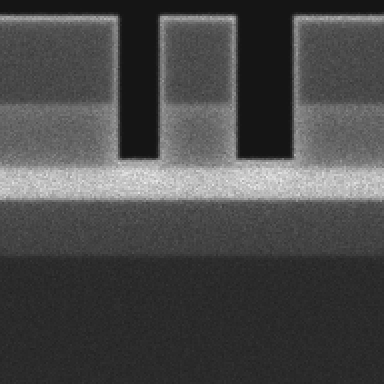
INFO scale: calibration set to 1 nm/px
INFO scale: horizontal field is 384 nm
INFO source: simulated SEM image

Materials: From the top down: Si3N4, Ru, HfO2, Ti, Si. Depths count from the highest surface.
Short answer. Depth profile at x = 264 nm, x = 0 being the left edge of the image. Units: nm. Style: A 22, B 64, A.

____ empty 144, Ru 8, HfO2 32, Ti 56, Si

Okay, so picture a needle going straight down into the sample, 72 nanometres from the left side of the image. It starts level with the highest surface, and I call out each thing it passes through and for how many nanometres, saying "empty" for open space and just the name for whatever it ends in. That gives Si3N4 88, Ru 64, HfO2 32, Ti 56, Si